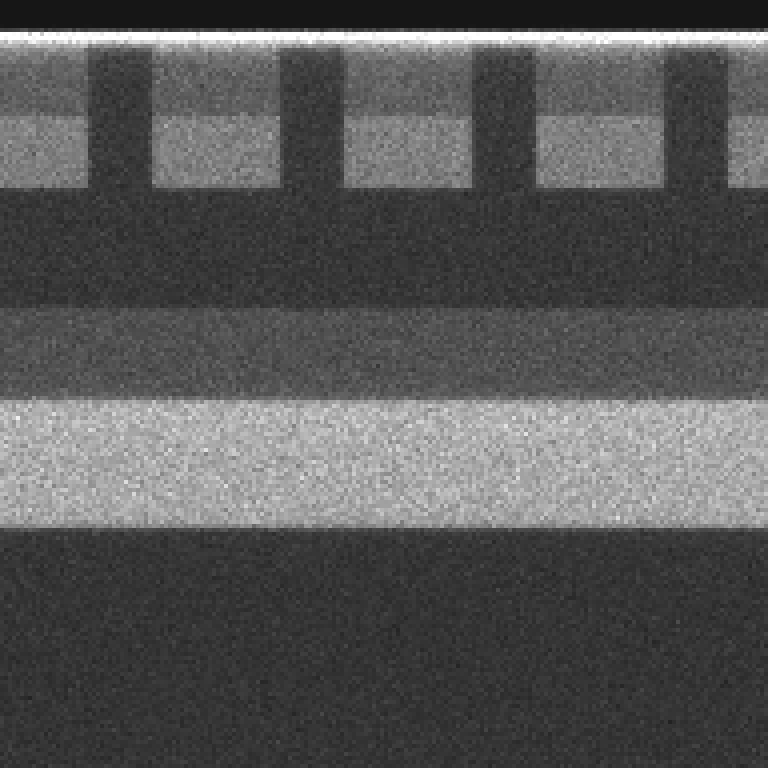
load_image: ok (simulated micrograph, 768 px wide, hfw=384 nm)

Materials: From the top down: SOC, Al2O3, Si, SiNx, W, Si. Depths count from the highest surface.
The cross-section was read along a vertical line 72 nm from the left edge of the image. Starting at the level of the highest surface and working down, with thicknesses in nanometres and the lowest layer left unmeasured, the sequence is SOC 6, Si 132, SiNx 46, W 64, Si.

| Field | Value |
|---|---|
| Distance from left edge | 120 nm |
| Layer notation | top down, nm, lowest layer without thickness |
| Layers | SOC 42, Al2O3 36, Si 60, SiNx 46, W 64, Si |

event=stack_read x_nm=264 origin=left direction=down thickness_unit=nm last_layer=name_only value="SOC 6, Si 132, SiNx 46, W 64, Si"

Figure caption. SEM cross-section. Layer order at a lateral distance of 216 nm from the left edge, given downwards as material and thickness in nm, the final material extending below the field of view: SOC 42, Al2O3 36, Si 60, SiNx 46, W 64, Si